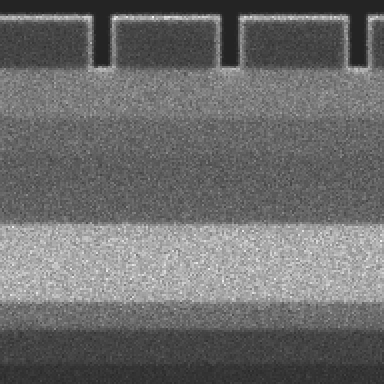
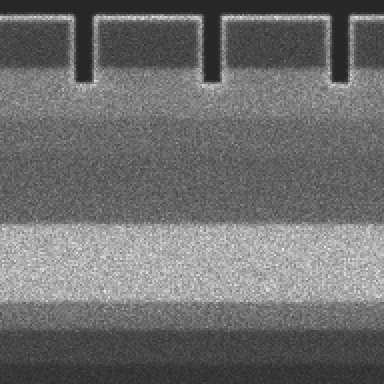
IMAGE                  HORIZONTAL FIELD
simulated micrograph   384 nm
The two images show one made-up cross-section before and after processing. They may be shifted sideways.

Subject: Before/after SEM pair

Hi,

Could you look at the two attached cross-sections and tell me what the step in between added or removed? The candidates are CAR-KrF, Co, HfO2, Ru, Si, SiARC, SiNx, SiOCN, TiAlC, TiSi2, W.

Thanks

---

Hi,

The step removed W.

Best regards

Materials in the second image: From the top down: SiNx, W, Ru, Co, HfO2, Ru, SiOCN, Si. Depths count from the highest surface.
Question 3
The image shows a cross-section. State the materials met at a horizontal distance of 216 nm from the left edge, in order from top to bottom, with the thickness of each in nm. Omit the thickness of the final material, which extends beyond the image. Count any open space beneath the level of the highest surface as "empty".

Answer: empty 68, W 34, Ru 36, Co 70, HfO2 78, Ru 28, SiOCN 34, Si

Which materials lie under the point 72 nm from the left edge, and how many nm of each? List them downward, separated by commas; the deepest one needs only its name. SiNx 52, W 50, Ru 36, Co 70, HfO2 78, Ru 28, SiOCN 34, Si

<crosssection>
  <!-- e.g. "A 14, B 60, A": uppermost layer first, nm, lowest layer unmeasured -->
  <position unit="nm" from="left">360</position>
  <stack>SiNx 52, W 50, Ru 36, Co 70, HfO2 78, Ru 28, SiOCN 34, Si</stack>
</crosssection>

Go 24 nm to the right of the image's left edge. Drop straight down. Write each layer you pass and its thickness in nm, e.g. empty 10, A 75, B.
SiNx 52, W 50, Ru 36, Co 70, HfO2 78, Ru 28, SiOCN 34, Si